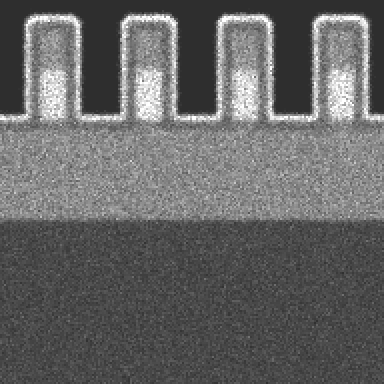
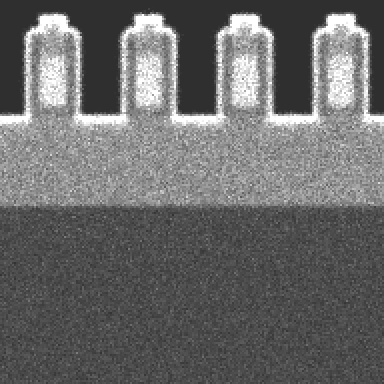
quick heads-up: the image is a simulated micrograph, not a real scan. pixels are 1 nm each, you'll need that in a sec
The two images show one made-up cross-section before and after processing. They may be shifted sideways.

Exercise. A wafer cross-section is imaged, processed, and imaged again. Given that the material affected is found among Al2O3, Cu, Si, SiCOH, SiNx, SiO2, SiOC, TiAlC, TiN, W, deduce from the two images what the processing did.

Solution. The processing removed SiNx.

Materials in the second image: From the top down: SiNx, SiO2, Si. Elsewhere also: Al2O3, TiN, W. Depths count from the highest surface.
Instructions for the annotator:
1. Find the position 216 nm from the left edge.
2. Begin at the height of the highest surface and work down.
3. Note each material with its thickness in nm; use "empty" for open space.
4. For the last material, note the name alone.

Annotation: empty 100, SiO2 90, Si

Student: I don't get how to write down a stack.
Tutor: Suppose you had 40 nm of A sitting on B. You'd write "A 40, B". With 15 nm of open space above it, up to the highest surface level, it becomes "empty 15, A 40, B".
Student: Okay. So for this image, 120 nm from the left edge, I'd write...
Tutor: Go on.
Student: empty 100, SiO2 90, Si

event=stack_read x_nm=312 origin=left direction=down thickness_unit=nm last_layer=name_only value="empty 100, SiO2 90, Si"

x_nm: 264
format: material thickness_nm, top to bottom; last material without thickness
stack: empty 12, SiNx 88, SiO2 90, Si